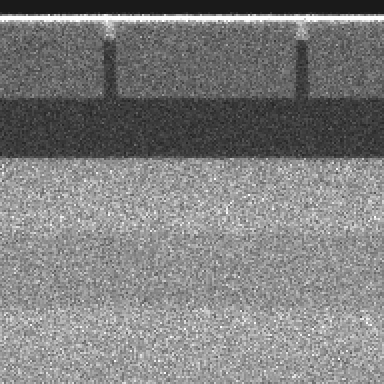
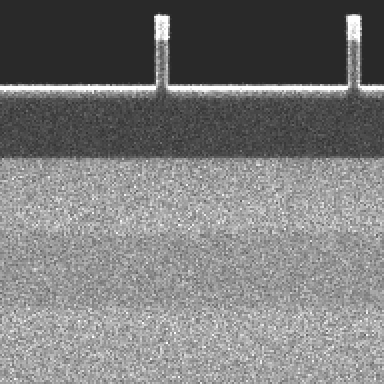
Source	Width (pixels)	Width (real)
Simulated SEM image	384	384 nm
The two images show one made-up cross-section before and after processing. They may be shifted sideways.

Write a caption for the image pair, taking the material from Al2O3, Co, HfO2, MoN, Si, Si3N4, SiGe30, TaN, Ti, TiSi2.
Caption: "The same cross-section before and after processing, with Si3N4 removed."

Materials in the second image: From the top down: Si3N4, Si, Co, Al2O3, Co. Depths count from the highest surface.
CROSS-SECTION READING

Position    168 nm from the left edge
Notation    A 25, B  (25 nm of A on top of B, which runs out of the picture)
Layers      empty 70, Si3N4 12, Si 60, Co 76, Al2O3 74, Co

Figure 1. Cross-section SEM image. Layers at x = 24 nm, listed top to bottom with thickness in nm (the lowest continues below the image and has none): empty 70, Si3N4 12, Si 60, Co 76, Al2O3 74, Co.